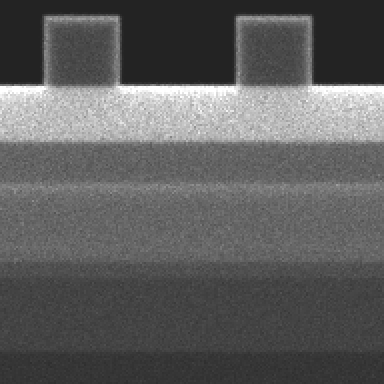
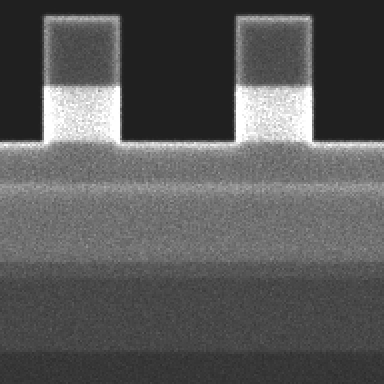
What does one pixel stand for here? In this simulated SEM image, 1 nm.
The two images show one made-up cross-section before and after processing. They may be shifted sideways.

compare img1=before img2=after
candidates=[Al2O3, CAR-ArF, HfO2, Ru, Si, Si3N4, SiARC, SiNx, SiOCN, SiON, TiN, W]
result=removed:HfO2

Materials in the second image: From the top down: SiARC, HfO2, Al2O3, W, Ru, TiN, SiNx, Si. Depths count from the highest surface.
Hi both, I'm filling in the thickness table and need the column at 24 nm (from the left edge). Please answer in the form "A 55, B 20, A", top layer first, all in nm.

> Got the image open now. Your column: empty 126, Al2O3 42, W 68, Ru 10, TiN 16, SiNx 74, Si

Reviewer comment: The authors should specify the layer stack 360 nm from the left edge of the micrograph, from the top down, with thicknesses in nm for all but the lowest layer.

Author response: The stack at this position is empty 126, Al2O3 42, W 68, Ru 10, TiN 16, SiNx 74, Si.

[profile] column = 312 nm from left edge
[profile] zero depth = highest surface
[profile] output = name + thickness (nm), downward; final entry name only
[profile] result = empty 126, Al2O3 42, W 68, Ru 10, TiN 16, SiNx 74, Si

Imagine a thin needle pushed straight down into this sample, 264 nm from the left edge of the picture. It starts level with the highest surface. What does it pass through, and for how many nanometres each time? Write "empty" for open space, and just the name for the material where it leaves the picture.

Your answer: SiARC 70, HfO2 56, Al2O3 42, W 68, Ru 10, TiN 16, SiNx 74, Si